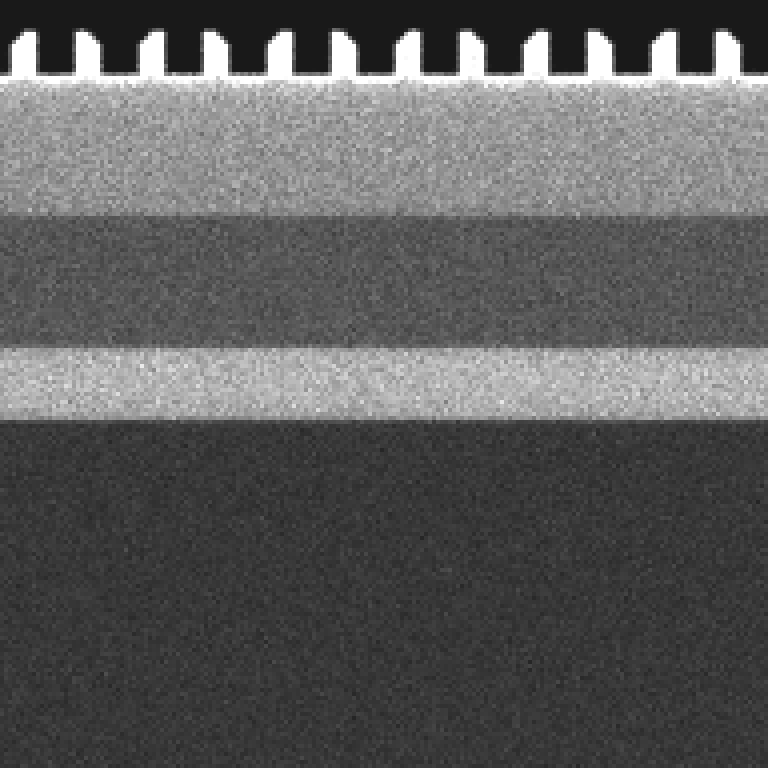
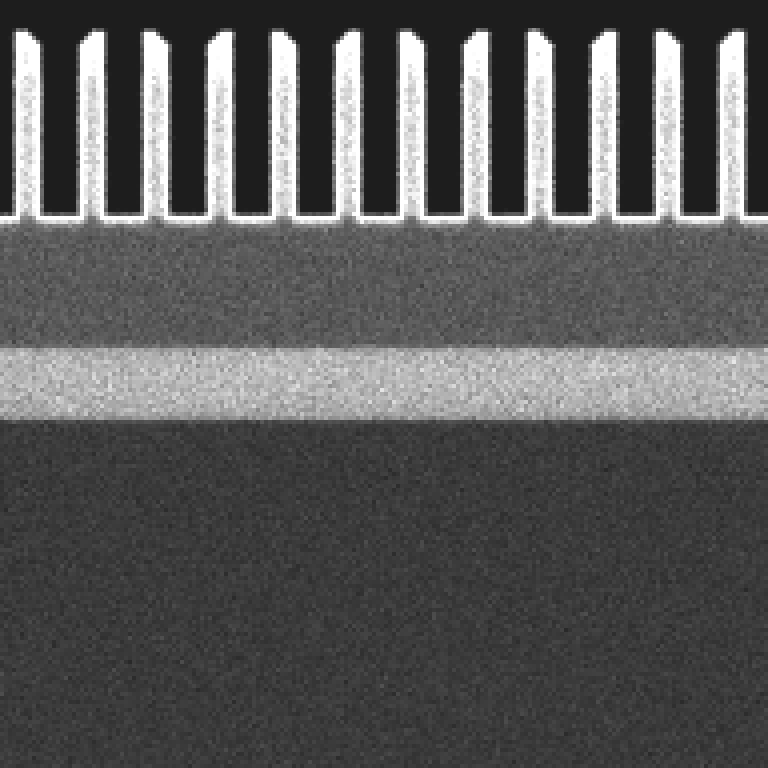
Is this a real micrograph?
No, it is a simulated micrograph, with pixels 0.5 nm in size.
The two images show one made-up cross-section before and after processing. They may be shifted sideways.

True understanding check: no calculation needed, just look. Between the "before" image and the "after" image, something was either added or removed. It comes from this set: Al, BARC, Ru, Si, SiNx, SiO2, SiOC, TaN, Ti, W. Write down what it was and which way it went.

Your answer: Ru (removed)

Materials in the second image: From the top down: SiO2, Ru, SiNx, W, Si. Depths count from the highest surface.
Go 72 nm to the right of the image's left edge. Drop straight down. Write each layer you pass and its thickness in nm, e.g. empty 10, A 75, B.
SiO2 22, Ru 70, SiNx 66, W 36, Si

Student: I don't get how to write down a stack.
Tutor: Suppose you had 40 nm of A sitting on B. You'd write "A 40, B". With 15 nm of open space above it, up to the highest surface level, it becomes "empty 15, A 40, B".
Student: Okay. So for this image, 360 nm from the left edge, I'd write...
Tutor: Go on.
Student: empty 6, SiO2 16, Ru 70, SiNx 66, W 36, Si